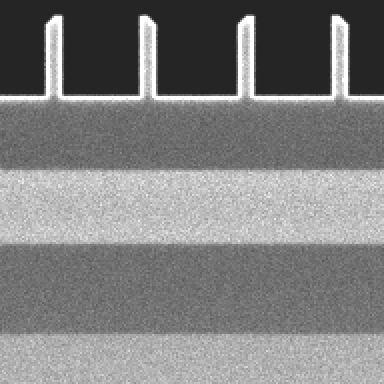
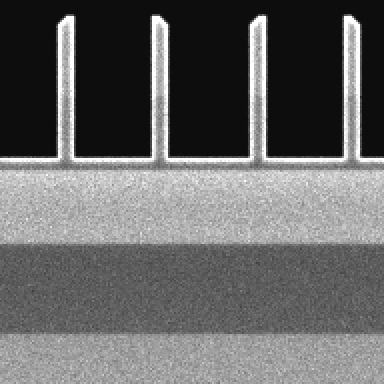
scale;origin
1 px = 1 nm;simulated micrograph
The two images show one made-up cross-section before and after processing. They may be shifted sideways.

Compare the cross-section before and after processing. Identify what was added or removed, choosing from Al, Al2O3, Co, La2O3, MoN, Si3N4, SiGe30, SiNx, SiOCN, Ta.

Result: SiOCN removed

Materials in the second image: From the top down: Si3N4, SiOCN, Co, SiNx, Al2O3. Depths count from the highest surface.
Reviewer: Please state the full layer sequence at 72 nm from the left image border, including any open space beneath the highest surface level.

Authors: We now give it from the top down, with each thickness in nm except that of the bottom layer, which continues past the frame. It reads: Si3N4 80, SiOCN 74, Co 74, SiNx 90, Al2O3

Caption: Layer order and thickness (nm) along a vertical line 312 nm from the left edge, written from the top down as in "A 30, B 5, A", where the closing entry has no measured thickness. empty 142, SiOCN 12, Co 74, SiNx 90, Al2O3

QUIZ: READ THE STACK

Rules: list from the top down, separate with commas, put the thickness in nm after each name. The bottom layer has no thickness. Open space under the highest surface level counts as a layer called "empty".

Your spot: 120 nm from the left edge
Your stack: empty 142, SiOCN 12, Co 74, SiNx 90, Al2O3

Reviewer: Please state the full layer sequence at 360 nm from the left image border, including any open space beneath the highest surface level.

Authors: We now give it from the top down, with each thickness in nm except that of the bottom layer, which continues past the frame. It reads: empty 142, SiOCN 12, Co 74, SiNx 90, Al2O3